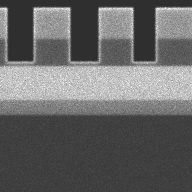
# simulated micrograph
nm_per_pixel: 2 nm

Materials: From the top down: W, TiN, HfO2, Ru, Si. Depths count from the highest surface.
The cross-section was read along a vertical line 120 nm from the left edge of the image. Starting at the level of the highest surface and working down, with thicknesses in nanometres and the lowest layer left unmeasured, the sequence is W 62, TiN 54, HfO2 68, Ru 30, Si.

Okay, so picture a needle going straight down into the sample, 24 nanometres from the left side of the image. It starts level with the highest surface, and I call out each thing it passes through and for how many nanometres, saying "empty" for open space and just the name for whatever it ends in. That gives empty 108, TiN 8, HfO2 68, Ru 30, Si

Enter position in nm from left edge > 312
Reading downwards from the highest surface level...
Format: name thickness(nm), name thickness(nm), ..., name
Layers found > W 62, TiN 54, HfO2 68, Ru 30, Si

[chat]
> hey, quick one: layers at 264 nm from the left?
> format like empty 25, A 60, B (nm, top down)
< W 62, TiN 54, HfO2 68, Ru 30, Si